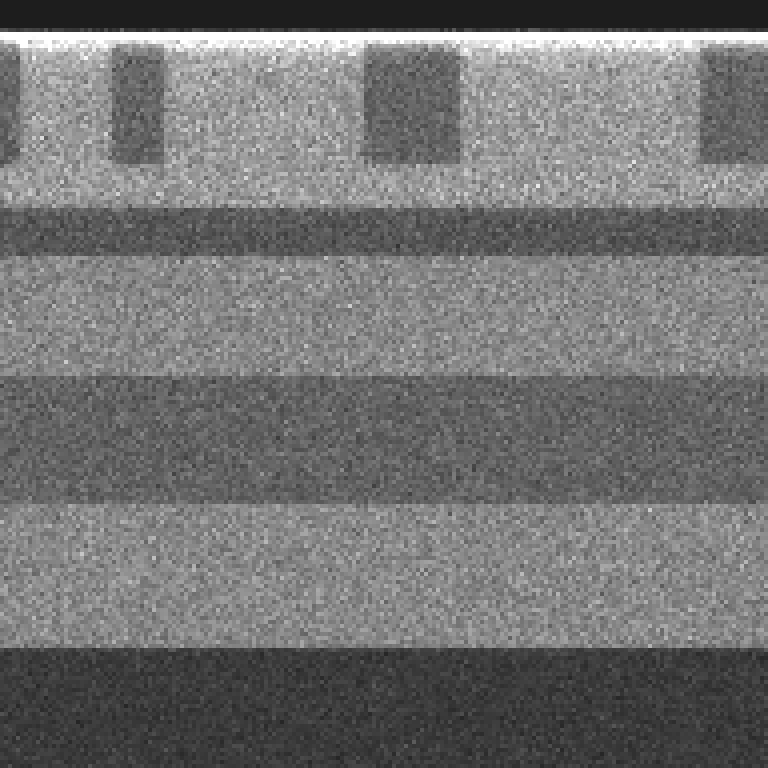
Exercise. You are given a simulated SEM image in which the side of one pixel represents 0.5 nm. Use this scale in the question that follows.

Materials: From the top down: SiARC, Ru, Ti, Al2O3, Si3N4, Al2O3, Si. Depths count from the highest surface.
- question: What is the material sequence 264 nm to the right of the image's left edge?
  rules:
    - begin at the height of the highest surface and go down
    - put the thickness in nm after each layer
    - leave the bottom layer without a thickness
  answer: SiARC 6, Ru 82, Ti 24, Al2O3 60, Si3N4 64, Al2O3 72, Si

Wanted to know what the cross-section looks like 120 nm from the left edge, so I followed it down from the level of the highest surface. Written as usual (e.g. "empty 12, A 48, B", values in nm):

SiARC 6, Ru 82, Ti 24, Al2O3 60, Si3N4 64, Al2O3 72, Si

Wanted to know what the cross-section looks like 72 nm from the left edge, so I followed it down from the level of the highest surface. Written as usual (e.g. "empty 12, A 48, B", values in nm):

SiARC 66, Ru 22, Ti 24, Al2O3 60, Si3N4 64, Al2O3 72, Si